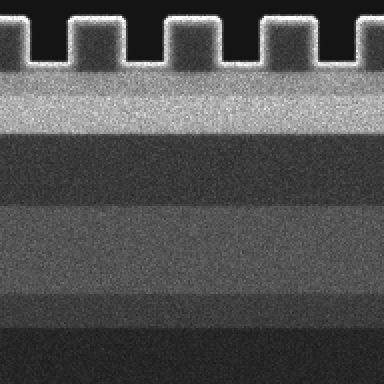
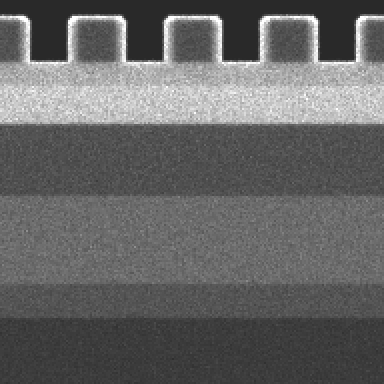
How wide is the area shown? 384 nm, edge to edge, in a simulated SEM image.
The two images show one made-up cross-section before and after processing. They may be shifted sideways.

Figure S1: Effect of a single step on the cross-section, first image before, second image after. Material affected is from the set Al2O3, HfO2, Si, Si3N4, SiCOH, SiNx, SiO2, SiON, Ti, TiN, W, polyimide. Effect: removed SiO2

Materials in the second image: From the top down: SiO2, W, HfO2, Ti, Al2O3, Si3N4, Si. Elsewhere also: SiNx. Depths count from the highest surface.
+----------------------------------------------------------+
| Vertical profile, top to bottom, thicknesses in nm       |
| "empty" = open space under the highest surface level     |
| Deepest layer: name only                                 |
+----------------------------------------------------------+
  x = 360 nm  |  SiO2 46, W 24, HfO2 38, Ti 72, Al2O3 88, Si3N4 34, Si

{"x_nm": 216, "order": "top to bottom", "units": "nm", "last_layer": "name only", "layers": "SiO2 46, W 24, HfO2 38, Ti 72, Al2O3 88, Si3N4 34, Si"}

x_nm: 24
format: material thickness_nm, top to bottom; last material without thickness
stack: SiO2 46, W 24, HfO2 38, Ti 72, Al2O3 88, Si3N4 34, Si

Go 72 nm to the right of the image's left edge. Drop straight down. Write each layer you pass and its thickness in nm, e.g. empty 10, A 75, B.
SiO2 46, W 24, HfO2 38, Ti 72, Al2O3 88, Si3N4 34, Si